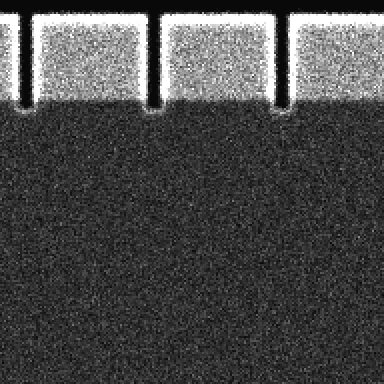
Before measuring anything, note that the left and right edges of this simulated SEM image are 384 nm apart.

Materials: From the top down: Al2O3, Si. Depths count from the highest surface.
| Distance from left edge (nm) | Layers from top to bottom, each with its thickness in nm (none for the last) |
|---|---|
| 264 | Al2O3 84, Si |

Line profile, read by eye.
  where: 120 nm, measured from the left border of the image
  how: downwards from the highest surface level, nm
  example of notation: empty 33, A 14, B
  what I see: Al2O3 84, Si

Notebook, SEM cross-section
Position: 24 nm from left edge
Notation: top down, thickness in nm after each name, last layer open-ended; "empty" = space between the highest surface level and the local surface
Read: empty 94, Si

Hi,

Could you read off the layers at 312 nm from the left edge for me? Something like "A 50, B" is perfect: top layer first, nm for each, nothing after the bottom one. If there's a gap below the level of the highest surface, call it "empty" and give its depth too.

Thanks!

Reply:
Al2O3 84, Si